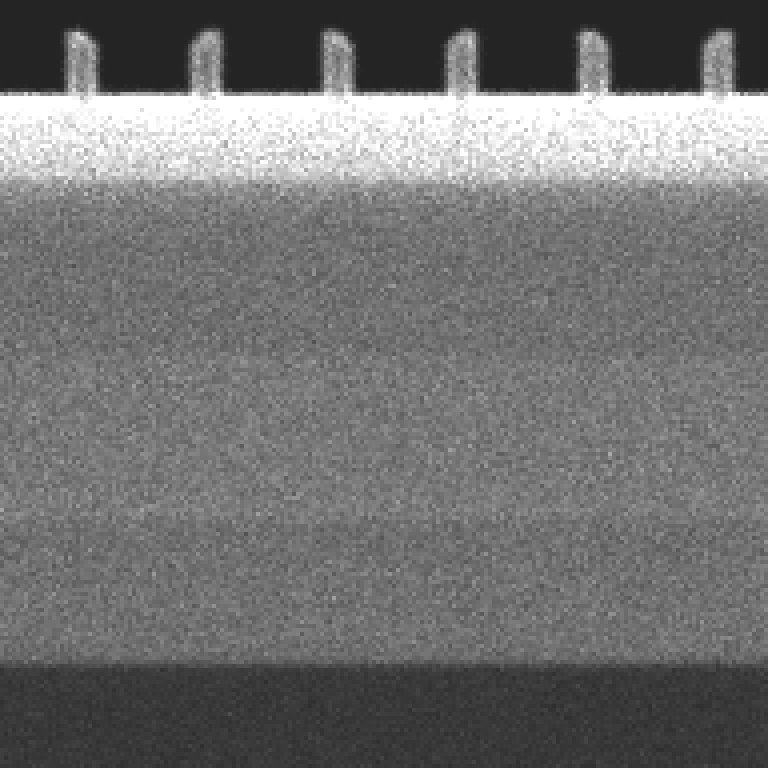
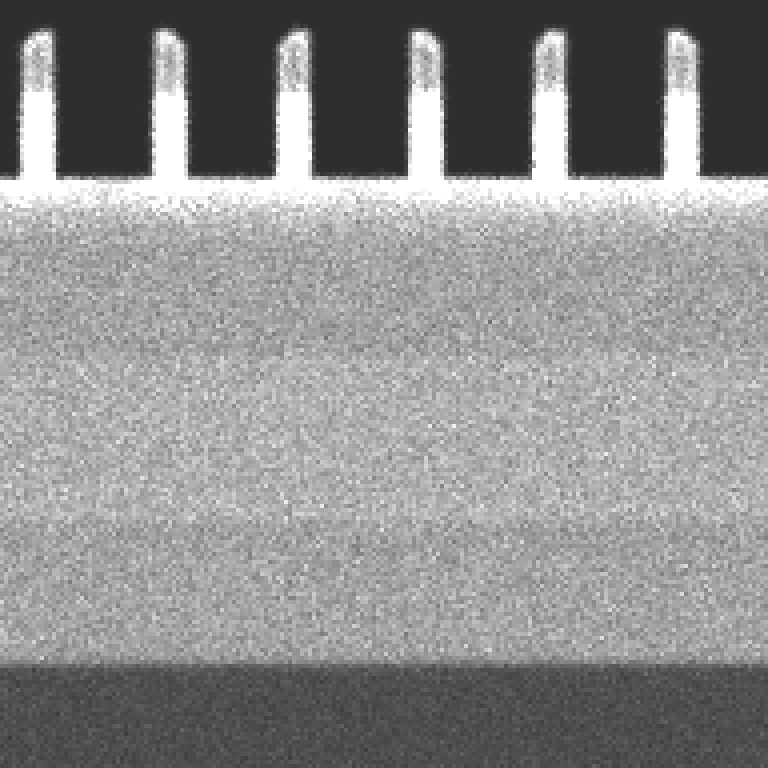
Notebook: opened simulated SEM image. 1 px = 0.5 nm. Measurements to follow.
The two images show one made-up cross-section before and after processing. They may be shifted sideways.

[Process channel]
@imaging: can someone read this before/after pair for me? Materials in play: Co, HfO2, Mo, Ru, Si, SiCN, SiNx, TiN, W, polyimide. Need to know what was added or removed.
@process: HfO2 removed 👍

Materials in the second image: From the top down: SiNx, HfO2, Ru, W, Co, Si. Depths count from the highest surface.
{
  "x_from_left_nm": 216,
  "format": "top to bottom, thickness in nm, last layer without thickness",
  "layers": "empty 4, SiNx 28, HfO2 42, Ru 88, W 82, Co 72, Si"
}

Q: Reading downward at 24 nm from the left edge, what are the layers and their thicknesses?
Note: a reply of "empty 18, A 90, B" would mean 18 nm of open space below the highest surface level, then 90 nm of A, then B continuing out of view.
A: SiNx 32, HfO2 42, Ru 88, W 82, Co 72, Si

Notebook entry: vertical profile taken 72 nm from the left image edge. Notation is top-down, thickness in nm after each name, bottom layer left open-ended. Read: empty 74, Ru 88, W 82, Co 72, Si